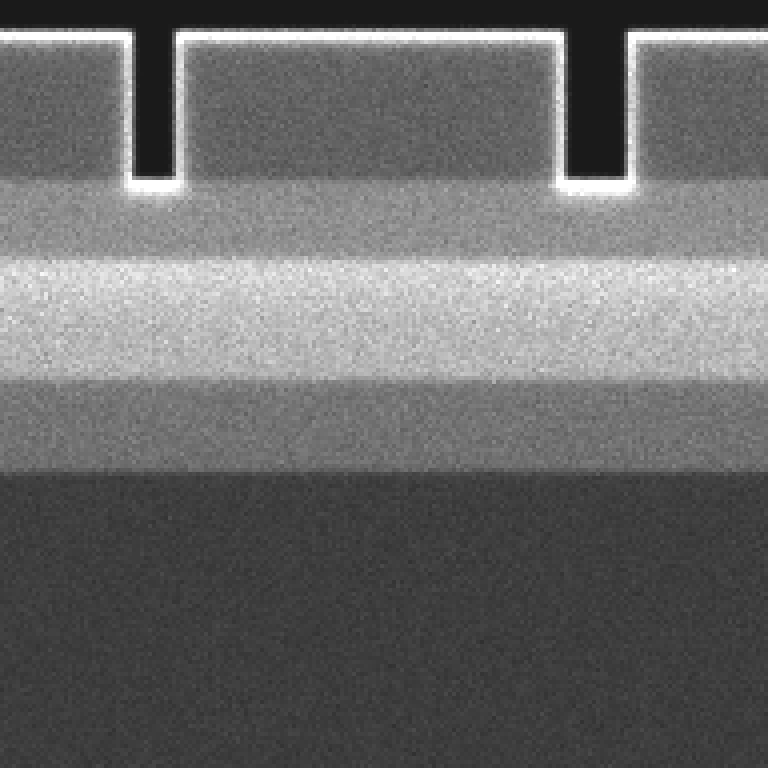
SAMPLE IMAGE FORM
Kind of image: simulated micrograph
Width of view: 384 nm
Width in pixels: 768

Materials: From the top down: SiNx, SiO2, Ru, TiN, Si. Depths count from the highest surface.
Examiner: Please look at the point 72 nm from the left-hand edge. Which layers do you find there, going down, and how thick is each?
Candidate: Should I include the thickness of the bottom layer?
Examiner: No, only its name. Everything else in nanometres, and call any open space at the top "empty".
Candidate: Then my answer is empty 74, SiO2 40, Ru 60, TiN 46, Si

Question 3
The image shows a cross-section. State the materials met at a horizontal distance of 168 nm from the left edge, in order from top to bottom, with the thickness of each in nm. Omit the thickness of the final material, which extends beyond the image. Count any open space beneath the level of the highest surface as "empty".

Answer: SiNx 74, SiO2 40, Ru 60, TiN 46, Si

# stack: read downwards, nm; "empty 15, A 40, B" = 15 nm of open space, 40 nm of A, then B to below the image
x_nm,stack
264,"SiNx 74, SiO2 40, Ru 60, TiN 46, Si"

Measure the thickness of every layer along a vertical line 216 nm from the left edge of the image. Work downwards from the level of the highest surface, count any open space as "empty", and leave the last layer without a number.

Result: SiNx 74, SiO2 40, Ru 60, TiN 46, Si